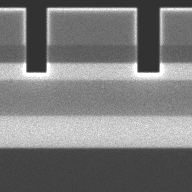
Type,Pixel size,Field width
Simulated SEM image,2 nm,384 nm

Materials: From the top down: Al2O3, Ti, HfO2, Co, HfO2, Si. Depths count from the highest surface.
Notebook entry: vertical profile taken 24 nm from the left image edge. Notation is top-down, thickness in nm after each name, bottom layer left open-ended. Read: Al2O3 74, Ti 36, HfO2 34, Co 72, HfO2 64, Si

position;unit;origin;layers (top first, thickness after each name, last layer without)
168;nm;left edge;Al2O3 74, Ti 36, HfO2 34, Co 72, HfO2 64, Si